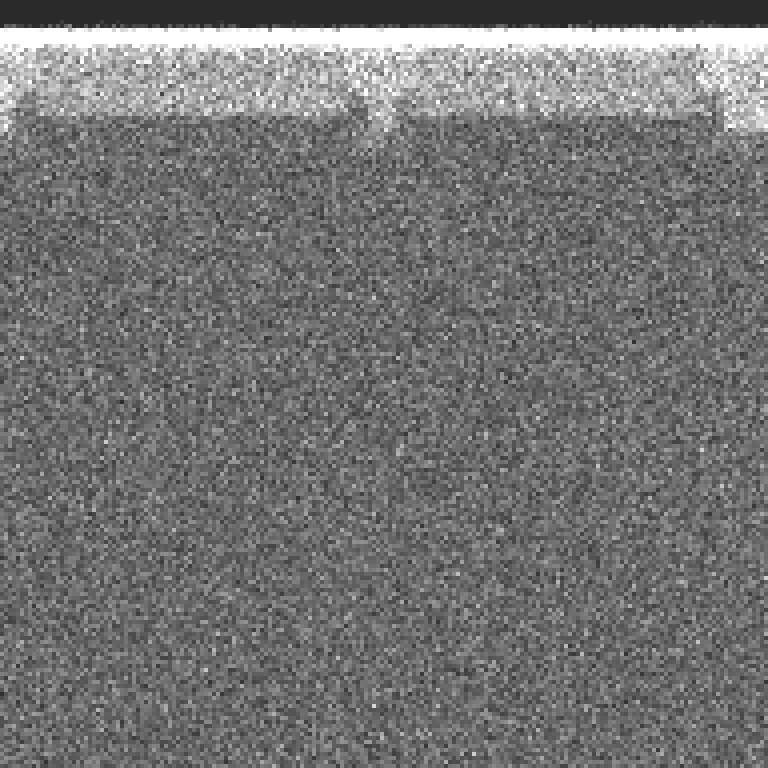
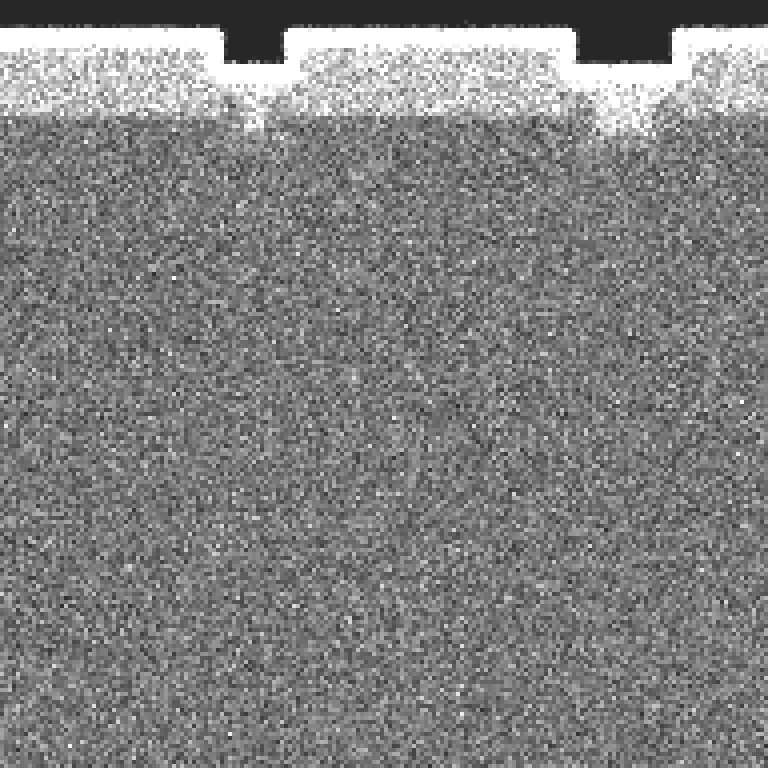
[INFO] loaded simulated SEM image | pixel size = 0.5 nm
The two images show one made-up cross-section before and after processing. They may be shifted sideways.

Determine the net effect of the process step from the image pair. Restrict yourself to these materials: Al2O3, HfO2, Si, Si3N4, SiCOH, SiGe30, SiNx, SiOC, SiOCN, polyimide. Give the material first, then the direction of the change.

Si3N4: removed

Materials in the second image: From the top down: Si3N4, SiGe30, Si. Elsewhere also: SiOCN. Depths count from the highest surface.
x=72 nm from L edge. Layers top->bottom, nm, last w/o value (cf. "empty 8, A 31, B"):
SiOCN 42, Si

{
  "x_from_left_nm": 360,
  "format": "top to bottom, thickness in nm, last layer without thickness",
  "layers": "SiOCN 42, Si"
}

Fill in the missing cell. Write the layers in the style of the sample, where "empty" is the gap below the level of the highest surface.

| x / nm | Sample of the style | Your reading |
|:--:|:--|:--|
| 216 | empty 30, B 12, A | SiOCN 42, Si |